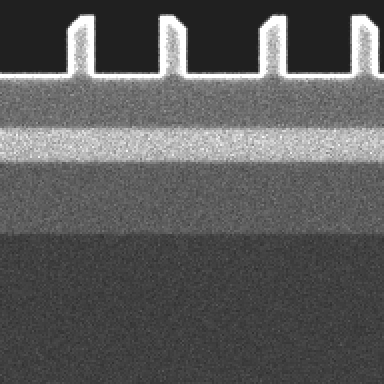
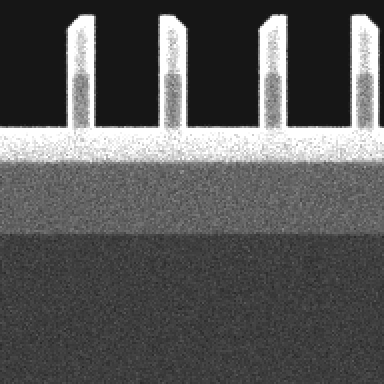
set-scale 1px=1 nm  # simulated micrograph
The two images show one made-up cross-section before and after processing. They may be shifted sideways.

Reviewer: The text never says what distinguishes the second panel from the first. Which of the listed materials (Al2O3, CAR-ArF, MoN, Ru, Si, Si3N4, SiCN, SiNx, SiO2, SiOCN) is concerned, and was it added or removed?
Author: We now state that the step removed Si3N4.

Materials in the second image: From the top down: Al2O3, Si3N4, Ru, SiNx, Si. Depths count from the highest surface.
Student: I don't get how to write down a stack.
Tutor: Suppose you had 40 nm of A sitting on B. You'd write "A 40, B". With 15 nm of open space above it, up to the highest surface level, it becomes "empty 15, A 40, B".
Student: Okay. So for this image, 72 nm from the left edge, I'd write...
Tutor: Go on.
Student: empty 8, Al2O3 50, Si3N4 54, Ru 34, SiNx 72, Si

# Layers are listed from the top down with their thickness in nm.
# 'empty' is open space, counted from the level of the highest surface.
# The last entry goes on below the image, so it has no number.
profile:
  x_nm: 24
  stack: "empty 112, Ru 34, SiNx 72, Si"